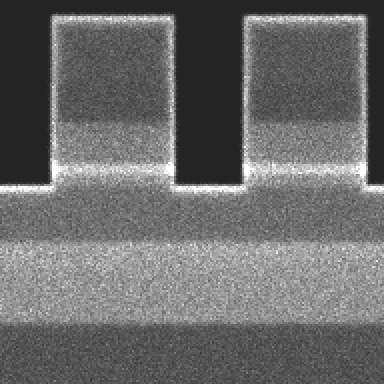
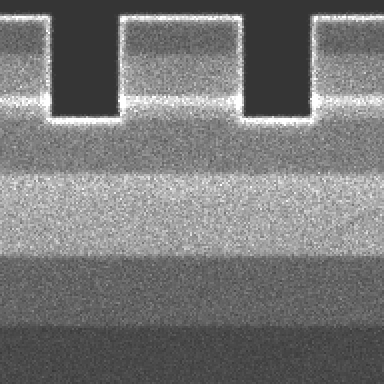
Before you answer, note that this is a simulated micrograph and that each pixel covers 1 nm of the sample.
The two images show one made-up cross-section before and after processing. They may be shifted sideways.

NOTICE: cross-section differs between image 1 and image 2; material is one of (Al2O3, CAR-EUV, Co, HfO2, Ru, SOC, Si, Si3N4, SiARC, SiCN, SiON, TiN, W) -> removed: SOC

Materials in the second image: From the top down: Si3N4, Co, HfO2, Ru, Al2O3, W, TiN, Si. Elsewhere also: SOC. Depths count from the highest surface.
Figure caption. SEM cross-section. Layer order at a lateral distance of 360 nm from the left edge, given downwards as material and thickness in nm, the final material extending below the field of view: Si3N4 38, Co 42, HfO2 10, Ru 12, Al2O3 56, W 82, TiN 70, Si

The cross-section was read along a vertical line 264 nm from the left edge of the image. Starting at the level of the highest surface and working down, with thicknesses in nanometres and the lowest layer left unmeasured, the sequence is empty 102, Al2O3 56, W 82, TiN 70, Si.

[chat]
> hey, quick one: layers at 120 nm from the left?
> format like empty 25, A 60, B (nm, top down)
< Si3N4 38, Co 42, HfO2 10, Ru 12, Al2O3 56, W 82, TiN 70, Si